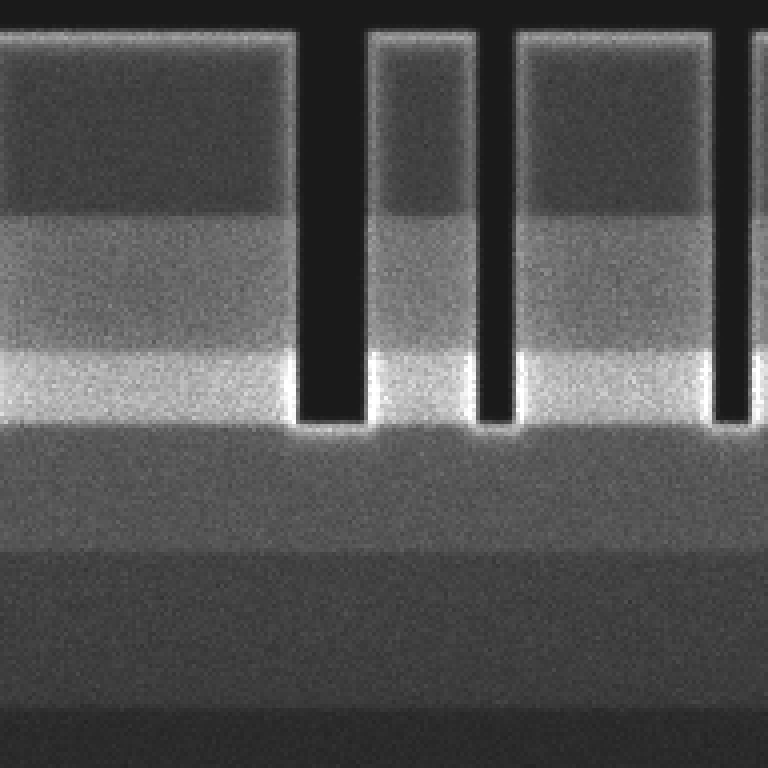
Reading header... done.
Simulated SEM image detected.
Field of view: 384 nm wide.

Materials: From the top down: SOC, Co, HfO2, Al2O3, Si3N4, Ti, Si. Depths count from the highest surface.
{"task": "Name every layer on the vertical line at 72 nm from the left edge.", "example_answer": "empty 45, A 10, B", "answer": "SOC 92, Co 68, HfO2 36, Al2O3 64, Si3N4 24, Ti 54, Si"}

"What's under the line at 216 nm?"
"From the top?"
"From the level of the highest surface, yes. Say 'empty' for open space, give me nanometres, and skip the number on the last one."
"SOC 92, Co 68, HfO2 36, Al2O3 64, Si3N4 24, Ti 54, Si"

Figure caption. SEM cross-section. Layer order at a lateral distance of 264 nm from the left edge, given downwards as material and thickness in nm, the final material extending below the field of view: SOC 92, Co 68, HfO2 36, Al2O3 64, Si3N4 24, Ti 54, Si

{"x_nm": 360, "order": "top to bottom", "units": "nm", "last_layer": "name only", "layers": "empty 196, Al2O3 64, Si3N4 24, Ti 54, Si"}